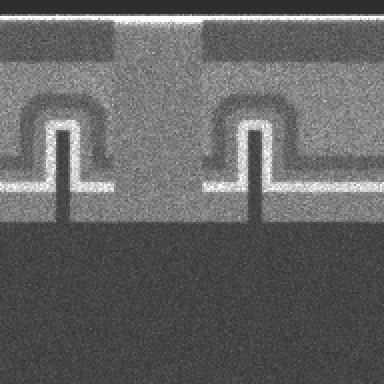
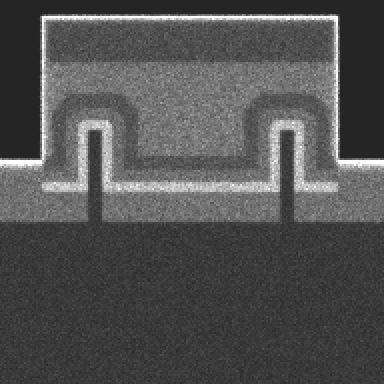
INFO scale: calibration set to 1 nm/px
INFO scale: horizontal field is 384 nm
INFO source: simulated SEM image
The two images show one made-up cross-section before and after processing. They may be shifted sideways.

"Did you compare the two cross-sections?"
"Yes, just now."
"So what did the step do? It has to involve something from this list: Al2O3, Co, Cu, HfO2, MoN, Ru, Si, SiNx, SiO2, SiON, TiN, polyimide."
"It removed SiO2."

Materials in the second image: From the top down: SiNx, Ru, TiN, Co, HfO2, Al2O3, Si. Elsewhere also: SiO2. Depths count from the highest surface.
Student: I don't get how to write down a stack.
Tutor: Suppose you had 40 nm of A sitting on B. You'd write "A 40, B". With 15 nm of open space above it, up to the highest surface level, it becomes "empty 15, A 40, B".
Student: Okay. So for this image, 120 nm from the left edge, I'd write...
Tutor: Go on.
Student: SiNx 46, Ru 32, TiN 22, Co 66, HfO2 10, Al2O3 30, Si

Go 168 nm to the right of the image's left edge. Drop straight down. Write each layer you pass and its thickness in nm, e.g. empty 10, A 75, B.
SiNx 46, Ru 94, TiN 14, Co 12, HfO2 10, Al2O3 30, Si